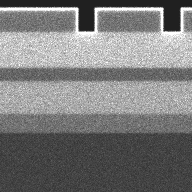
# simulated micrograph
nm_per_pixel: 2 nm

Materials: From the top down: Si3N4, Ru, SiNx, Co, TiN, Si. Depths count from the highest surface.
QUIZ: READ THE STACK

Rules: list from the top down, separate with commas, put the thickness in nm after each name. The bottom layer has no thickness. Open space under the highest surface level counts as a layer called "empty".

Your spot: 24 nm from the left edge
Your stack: Si3N4 48, Ru 72, SiNx 26, Co 66, TiN 38, Si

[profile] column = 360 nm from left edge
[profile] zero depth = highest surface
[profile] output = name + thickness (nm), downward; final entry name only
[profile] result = empty 48, Ru 72, SiNx 26, Co 66, TiN 38, Si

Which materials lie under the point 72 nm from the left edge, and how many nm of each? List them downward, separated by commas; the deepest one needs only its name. Si3N4 48, Ru 72, SiNx 26, Co 66, TiN 38, Si